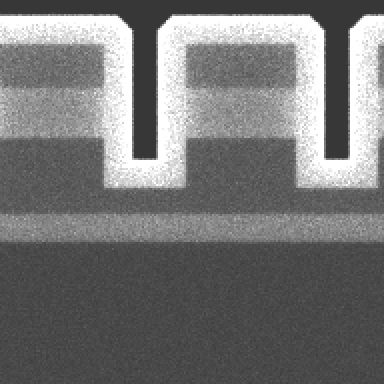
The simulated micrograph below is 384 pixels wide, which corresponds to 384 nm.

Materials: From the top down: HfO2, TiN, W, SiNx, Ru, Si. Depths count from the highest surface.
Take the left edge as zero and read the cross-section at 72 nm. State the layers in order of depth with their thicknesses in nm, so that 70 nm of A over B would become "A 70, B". HfO2 28, TiN 44, W 50, SiNx 76, Ru 28, Si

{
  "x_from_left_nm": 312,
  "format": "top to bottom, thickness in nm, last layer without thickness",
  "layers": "empty 4, HfO2 168, SiNx 26, Ru 28, Si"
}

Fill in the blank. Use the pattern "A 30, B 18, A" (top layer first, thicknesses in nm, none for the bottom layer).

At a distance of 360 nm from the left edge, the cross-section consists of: empty 4, HfO2 168, SiNx 26, Ru 28, Si